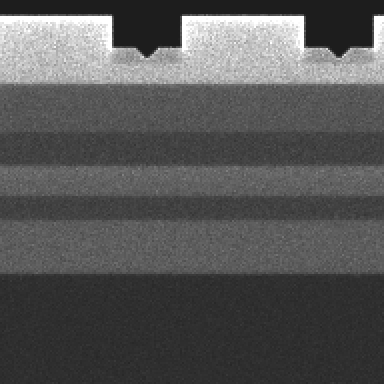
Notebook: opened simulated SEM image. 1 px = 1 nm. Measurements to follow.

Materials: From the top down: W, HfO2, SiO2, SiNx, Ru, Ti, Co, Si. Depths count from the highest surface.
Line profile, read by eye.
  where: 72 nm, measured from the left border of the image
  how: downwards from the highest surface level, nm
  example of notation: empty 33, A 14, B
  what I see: HfO2 68, SiO2 48, SiNx 34, Ru 30, Ti 24, Co 54, Si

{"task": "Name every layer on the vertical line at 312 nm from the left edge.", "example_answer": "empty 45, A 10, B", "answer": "empty 32, W 16, HfO2 20, SiO2 48, SiNx 34, Ru 30, Ti 24, Co 54, Si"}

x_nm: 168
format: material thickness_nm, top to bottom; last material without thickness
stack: empty 32, W 16, HfO2 20, SiO2 48, SiNx 34, Ru 30, Ti 24, Co 54, Si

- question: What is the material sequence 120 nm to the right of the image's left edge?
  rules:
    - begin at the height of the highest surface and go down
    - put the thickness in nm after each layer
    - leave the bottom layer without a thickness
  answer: empty 32, W 16, HfO2 20, SiO2 48, SiNx 34, Ru 30, Ti 24, Co 54, Si